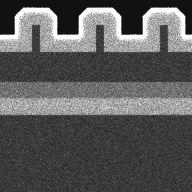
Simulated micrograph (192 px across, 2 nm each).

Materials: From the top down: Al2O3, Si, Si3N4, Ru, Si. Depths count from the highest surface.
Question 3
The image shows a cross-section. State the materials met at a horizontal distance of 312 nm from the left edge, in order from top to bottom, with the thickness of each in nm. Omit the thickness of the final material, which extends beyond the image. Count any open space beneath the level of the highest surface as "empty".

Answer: Al2O3 88, Si 60, Si3N4 32, Ru 34, Si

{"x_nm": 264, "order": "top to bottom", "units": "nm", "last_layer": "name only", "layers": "empty 54, Al2O3 34, Si 60, Si3N4 32, Ru 34, Si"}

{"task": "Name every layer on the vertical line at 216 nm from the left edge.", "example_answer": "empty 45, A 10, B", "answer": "Al2O3 88, Si 60, Si3N4 32, Ru 34, Si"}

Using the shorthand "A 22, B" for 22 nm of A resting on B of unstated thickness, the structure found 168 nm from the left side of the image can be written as empty 6, Al2O3 82, Si 60, Si3N4 32, Ru 34, Si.